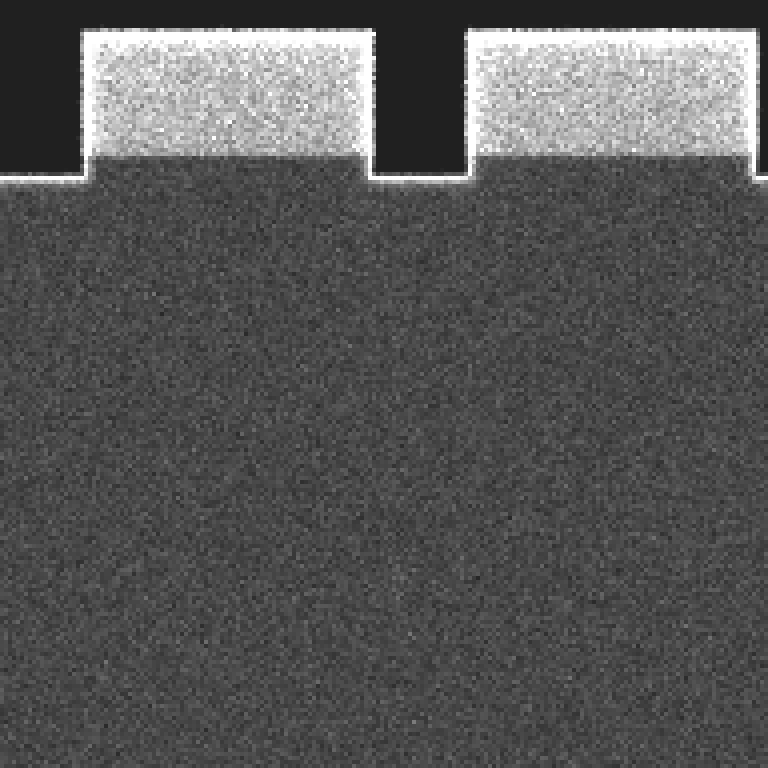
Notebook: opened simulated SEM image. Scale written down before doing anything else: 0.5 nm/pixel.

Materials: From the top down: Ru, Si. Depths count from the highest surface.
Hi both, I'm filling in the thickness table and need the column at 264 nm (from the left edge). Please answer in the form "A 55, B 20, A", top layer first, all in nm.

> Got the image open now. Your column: Ru 62, Si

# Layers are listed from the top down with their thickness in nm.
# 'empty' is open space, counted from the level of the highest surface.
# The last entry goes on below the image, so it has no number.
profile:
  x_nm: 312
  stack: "Ru 62, Si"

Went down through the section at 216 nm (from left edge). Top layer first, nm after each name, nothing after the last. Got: empty 72, Si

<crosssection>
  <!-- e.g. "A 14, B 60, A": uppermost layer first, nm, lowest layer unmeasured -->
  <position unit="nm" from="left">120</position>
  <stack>Ru 62, Si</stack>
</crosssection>